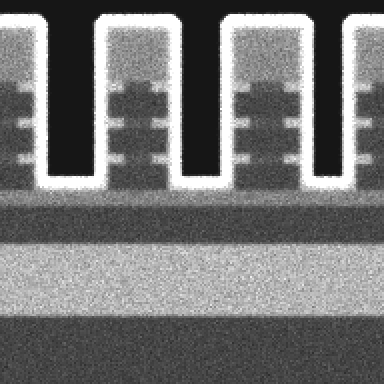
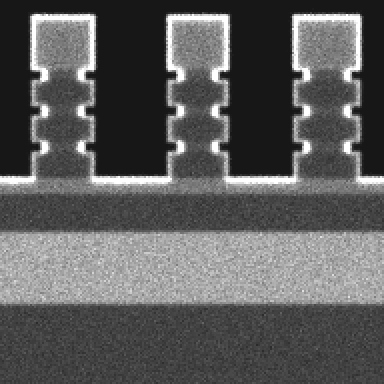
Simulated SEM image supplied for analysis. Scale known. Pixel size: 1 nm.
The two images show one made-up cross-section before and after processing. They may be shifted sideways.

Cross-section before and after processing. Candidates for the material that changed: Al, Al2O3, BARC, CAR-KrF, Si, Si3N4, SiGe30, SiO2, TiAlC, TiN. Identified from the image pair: Al2O3 (removed).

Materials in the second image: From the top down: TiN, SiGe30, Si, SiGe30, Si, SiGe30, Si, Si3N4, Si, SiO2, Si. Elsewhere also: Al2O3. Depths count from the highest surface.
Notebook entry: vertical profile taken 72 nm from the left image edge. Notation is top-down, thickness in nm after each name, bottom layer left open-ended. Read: TiN 54, SiGe30 10, Si 26, SiGe30 10, Si 26, SiGe30 10, Si 26, Si3N4 16, Si 38, SiO2 72, Si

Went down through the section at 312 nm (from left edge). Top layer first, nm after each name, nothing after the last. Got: TiN 54, SiGe30 10, Si 26, SiGe30 10, Si 26, SiGe30 10, Si 26, Si3N4 16, Si 38, SiO2 72, Si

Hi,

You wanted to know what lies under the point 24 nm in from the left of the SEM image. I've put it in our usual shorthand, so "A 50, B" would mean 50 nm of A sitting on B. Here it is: empty 162, Si3N4 16, Si 38, SiO2 72, Si